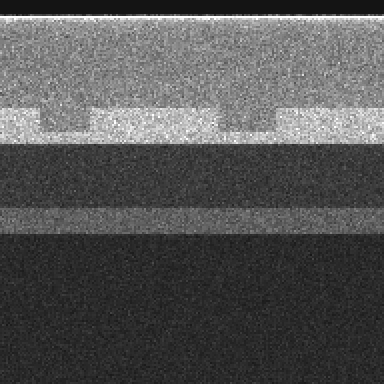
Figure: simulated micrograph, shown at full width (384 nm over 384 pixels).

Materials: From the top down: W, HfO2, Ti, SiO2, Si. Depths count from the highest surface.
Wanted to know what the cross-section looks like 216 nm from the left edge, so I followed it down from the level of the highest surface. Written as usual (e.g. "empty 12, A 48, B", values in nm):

W 92, HfO2 36, Ti 64, SiO2 26, Si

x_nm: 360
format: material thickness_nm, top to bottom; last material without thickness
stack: W 92, HfO2 36, Ti 64, SiO2 26, Si